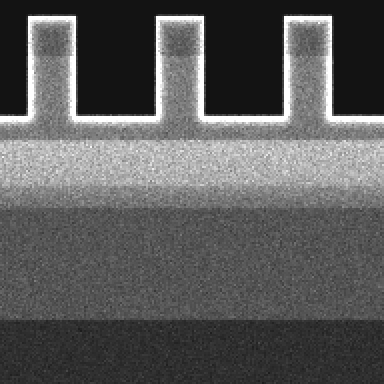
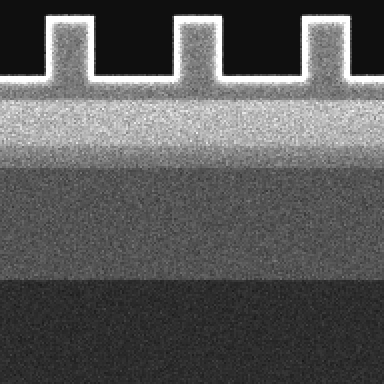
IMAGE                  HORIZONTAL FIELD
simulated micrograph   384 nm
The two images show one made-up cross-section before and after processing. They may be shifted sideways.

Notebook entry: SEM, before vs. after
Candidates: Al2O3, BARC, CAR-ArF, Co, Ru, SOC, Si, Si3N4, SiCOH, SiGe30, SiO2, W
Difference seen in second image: SOC removed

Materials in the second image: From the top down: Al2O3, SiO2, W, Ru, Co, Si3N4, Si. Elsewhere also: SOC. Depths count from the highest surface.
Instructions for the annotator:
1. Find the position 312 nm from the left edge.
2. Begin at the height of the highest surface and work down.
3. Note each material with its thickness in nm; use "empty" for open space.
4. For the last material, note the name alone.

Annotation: Al2O3 60, SiO2 24, W 46, Ru 10, Co 12, Si3N4 112, Si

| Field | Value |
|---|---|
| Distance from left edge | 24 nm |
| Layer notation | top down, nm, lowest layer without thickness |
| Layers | empty 60, SiO2 24, W 46, Ru 10, Co 12, Si3N4 112, Si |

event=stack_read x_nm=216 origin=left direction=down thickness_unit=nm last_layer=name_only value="Al2O3 60, SiO2 24, W 46, Ru 10, Co 12, Si3N4 112, Si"